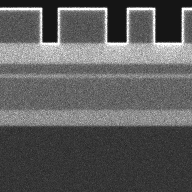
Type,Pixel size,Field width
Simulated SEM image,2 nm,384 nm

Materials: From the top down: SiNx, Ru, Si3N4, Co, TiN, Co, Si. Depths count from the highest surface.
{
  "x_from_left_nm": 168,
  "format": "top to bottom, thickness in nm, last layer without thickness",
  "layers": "SiNx 70, Ru 42, Si3N4 20, Co 8, TiN 64, Co 32, Si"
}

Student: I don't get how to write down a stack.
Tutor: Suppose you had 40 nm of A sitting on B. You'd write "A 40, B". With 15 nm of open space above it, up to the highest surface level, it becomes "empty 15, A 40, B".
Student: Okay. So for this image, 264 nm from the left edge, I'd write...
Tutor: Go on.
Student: SiNx 70, Ru 42, Si3N4 20, Co 8, TiN 64, Co 32, Si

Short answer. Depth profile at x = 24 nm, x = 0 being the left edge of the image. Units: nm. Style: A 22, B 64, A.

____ SiNx 70, Ru 42, Si3N4 20, Co 8, TiN 64, Co 32, Si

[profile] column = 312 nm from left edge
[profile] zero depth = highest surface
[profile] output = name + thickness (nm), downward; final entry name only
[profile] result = empty 70, Ru 42, Si3N4 20, Co 8, TiN 64, Co 32, Si